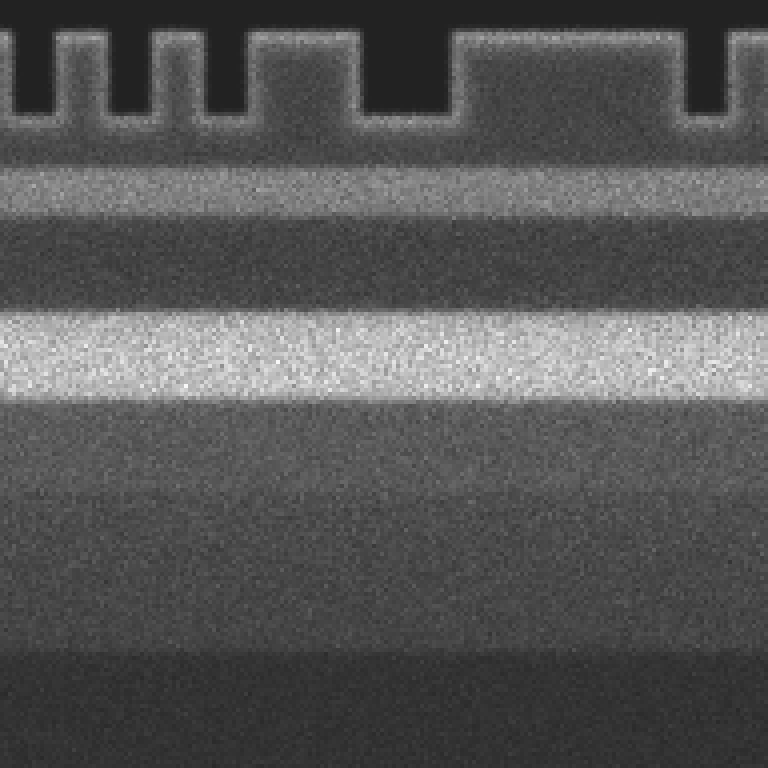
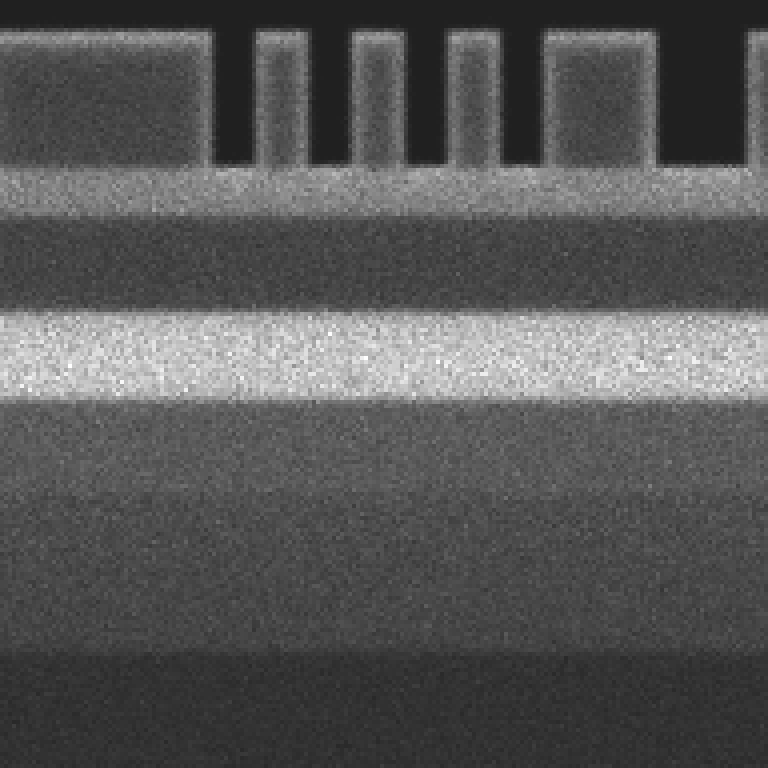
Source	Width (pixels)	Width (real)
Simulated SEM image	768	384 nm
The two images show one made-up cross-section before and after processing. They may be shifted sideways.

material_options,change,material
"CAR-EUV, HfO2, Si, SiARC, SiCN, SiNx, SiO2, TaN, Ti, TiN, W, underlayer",removed,underlayer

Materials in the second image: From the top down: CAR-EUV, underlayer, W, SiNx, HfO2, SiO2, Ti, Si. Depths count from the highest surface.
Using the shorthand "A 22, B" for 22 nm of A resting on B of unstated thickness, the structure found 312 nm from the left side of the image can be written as CAR-EUV 42, underlayer 26, W 24, SiNx 48, HfO2 44, SiO2 46, Ti 80, Si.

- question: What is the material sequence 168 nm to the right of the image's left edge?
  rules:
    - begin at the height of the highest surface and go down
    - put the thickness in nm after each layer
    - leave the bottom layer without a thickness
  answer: empty 68, W 24, SiNx 48, HfO2 44, SiO2 46, Ti 80, Si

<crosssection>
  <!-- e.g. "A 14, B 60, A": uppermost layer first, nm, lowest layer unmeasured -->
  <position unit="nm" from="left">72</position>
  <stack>CAR-EUV 42, underlayer 26, W 24, SiNx 48, HfO2 44, SiO2 46, Ti 80, Si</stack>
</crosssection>